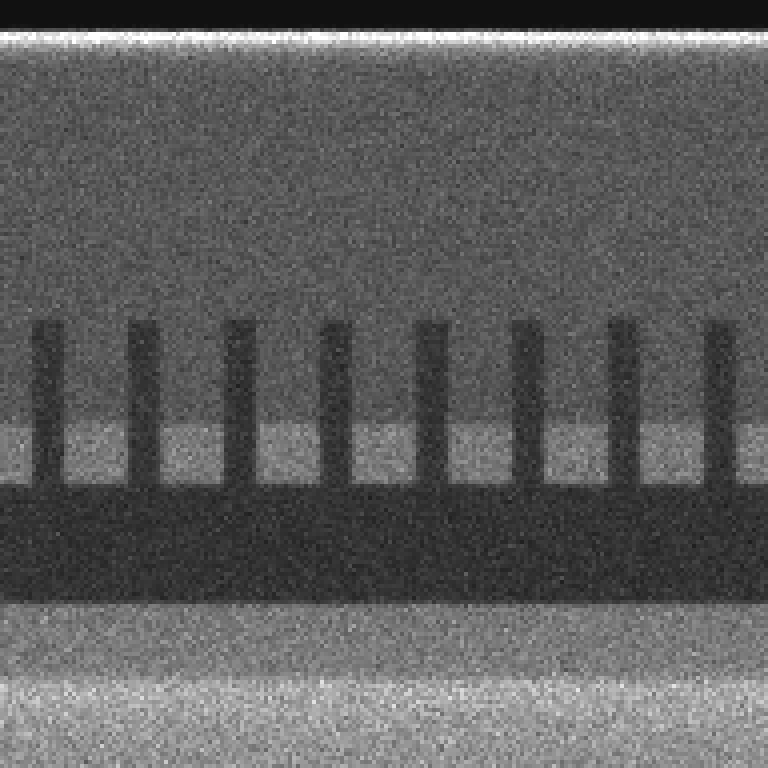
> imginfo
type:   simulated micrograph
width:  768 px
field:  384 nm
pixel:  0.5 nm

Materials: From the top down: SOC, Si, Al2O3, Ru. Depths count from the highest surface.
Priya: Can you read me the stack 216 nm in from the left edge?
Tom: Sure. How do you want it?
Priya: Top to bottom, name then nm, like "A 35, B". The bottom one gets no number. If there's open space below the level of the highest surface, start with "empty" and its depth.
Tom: SOC 144, Si 142, Al2O3 38, Ru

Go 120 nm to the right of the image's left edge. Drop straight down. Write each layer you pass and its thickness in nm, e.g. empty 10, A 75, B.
SOC 144, Si 142, Al2O3 38, Ru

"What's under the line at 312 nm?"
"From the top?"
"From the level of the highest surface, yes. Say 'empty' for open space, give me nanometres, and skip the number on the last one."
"SOC 144, Si 142, Al2O3 38, Ru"